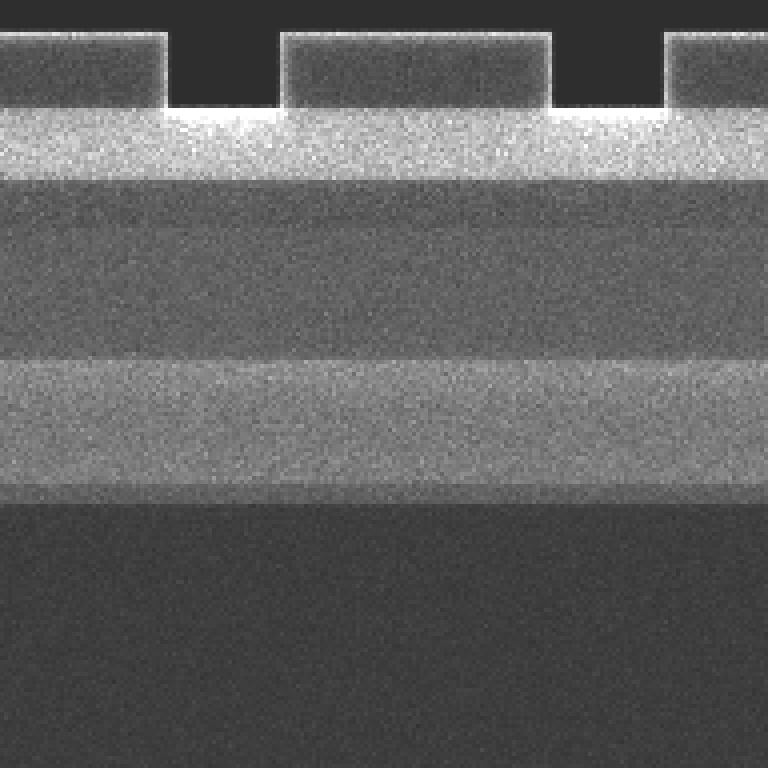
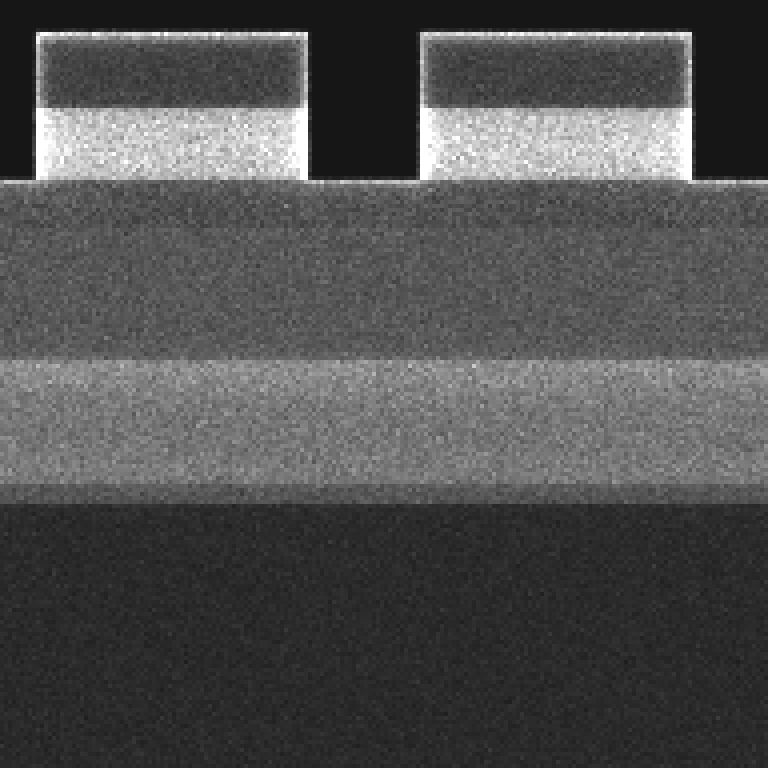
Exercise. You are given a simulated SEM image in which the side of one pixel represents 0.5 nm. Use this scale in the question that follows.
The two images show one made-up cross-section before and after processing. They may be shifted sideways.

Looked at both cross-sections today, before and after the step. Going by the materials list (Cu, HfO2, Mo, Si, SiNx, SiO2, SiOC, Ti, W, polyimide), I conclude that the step removed HfO2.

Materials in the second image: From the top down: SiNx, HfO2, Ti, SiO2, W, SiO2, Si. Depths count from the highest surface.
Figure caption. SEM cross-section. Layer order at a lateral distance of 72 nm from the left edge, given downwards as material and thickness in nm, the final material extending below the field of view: SiNx 38, HfO2 36, Ti 24, SiO2 66, W 62, SiO2 10, Si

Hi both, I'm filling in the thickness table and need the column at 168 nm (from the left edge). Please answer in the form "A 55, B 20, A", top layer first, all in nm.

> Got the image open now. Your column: empty 74, Ti 24, SiO2 66, W 62, SiO2 10, Si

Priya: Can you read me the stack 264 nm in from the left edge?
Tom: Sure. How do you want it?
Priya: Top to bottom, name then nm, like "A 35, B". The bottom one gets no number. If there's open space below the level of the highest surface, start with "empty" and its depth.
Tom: SiNx 38, HfO2 36, Ti 24, SiO2 66, W 62, SiO2 10, Si